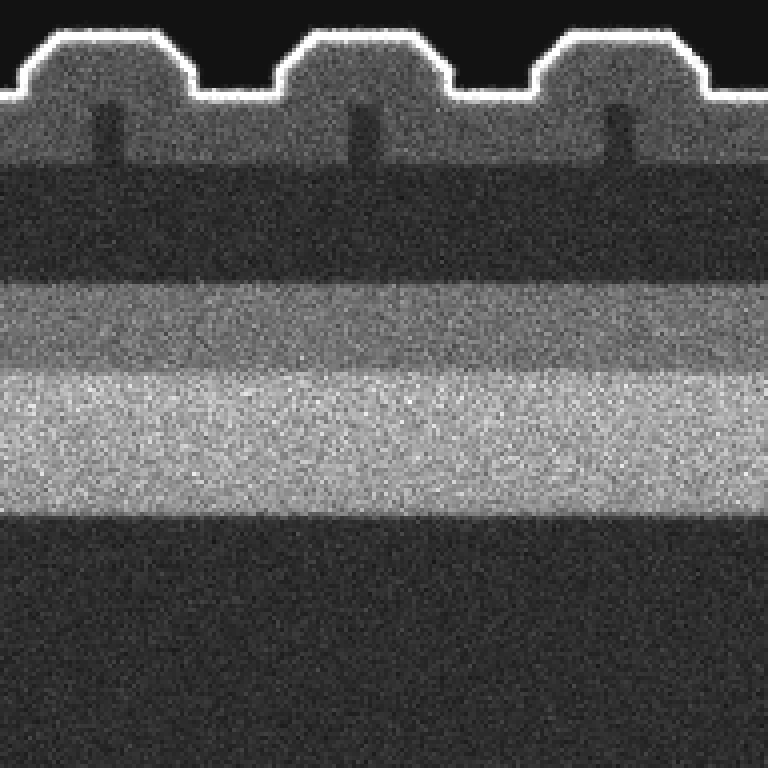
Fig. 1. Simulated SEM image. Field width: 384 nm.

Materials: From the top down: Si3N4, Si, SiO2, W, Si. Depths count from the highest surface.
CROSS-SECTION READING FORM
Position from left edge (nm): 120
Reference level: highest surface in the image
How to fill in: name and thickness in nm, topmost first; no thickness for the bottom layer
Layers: empty 30, Si3N4 36, Si 60, SiO2 44, W 72, Si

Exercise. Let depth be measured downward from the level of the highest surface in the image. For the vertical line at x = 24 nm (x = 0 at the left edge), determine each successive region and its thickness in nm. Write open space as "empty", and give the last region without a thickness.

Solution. empty 4, Si3N4 62, Si 60, SiO2 44, W 72, Si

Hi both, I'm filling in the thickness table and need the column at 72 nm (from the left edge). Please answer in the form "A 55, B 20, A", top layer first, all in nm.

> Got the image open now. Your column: Si3N4 66, Si 60, SiO2 44, W 72, Si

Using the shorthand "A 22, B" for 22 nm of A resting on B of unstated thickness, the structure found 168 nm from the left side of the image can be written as Si3N4 66, Si 60, SiO2 44, W 72, Si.